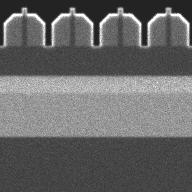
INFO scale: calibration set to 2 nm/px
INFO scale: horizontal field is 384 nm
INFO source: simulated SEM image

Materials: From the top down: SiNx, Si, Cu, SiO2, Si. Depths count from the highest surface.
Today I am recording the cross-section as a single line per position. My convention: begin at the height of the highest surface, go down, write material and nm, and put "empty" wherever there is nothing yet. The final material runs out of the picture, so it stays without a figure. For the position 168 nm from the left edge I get empty 14, SiNx 62, Si 60, Cu 34, SiO2 88, Si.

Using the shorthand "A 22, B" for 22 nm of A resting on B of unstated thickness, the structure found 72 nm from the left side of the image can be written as empty 14, SiNx 62, Si 60, Cu 34, SiO2 88, Si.